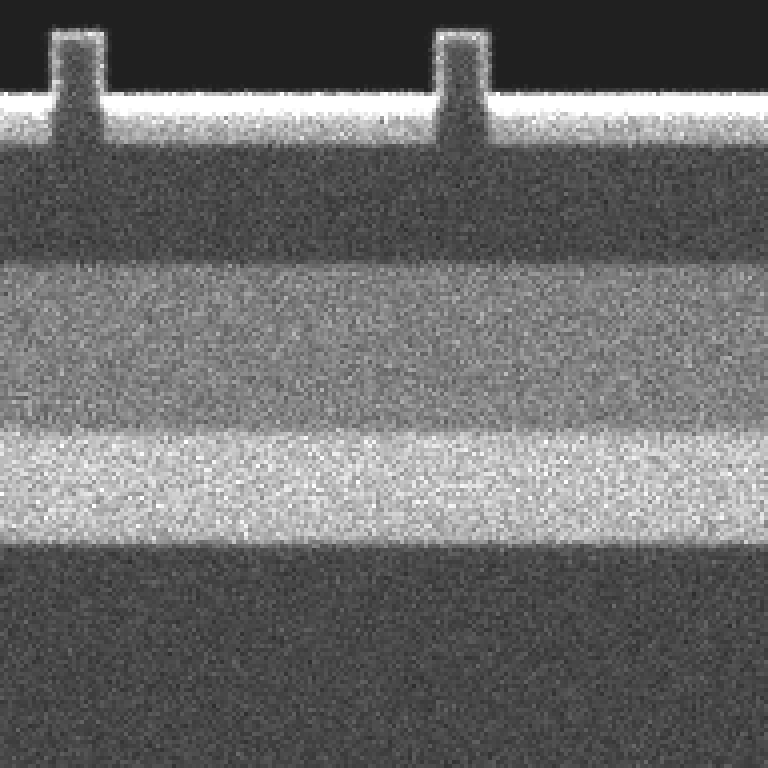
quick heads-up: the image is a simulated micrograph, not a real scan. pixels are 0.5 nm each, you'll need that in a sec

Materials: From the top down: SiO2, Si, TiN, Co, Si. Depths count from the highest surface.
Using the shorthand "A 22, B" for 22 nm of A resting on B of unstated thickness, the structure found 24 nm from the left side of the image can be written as empty 32, SiO2 24, Si 60, TiN 84, Co 56, Si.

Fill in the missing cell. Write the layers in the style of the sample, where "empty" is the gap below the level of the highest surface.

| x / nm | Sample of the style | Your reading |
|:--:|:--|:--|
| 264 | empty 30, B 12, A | empty 32, SiO2 24, Si 60, TiN 84, Co 56, Si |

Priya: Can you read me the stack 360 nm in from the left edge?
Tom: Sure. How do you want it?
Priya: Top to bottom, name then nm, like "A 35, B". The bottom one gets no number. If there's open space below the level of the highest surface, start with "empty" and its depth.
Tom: empty 32, SiO2 24, Si 60, TiN 84, Co 56, Si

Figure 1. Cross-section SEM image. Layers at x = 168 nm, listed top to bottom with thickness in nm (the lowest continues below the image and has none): empty 32, SiO2 24, Si 60, TiN 84, Co 56, Si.